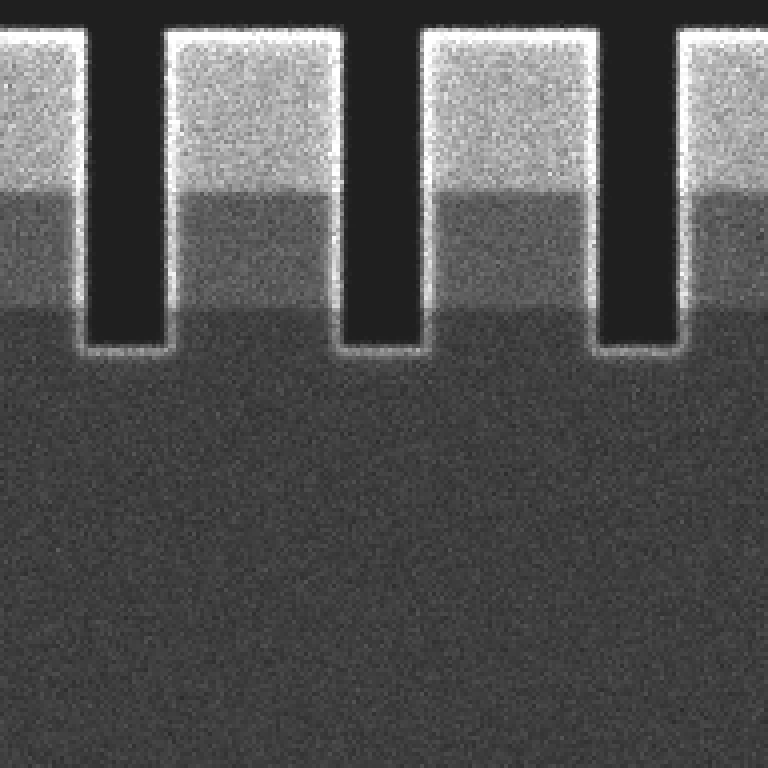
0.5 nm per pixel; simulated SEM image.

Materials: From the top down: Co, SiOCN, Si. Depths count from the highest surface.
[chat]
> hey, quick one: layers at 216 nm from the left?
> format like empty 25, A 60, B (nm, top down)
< Co 80, SiOCN 58, Si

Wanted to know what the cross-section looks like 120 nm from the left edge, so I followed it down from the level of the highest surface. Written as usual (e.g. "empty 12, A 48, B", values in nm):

Co 80, SiOCN 58, Si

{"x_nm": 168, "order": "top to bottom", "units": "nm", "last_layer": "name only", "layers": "Co 80, SiOCN 58, Si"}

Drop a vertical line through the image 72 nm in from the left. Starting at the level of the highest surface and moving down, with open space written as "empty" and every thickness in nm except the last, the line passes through empty 158, Si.